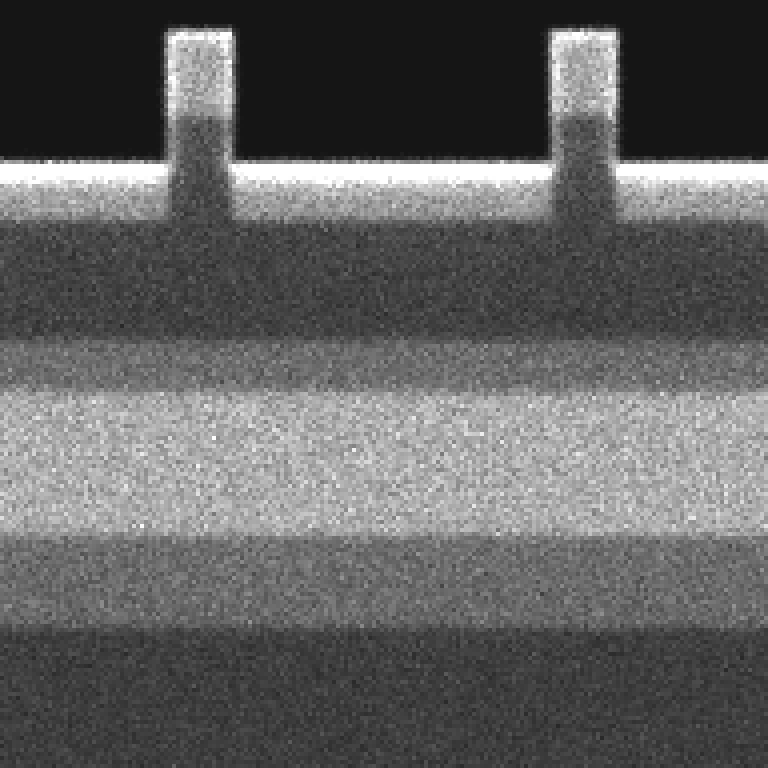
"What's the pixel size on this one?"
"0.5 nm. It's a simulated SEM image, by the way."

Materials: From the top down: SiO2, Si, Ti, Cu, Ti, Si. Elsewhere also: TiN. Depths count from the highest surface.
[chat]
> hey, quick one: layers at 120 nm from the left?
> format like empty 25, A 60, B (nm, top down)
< empty 66, SiO2 28, Si 60, Ti 26, Cu 72, Ti 46, Si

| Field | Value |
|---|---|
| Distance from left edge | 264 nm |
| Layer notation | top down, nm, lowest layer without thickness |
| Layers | empty 66, SiO2 28, Si 60, Ti 26, Cu 72, Ti 46, Si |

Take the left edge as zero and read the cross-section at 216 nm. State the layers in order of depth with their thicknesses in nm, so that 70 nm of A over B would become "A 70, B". empty 66, SiO2 28, Si 60, Ti 26, Cu 72, Ti 46, Si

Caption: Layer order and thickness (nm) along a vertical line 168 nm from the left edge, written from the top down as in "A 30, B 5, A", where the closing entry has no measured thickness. empty 66, SiO2 28, Si 60, Ti 26, Cu 72, Ti 46, Si